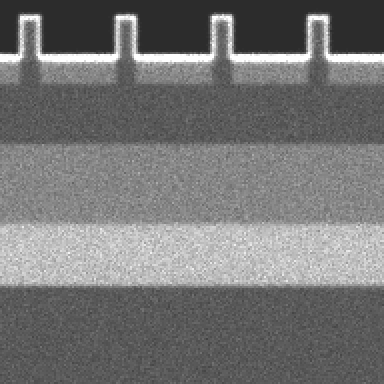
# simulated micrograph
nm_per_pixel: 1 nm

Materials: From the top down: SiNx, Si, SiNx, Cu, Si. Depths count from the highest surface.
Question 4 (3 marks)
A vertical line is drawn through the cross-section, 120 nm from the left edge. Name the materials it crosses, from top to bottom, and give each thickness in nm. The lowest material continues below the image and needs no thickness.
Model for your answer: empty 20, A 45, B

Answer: Si 128, SiNx 80, Cu 62, Si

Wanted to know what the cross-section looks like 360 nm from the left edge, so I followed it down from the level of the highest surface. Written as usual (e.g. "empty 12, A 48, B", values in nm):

empty 40, SiNx 28, Si 60, SiNx 80, Cu 62, Si